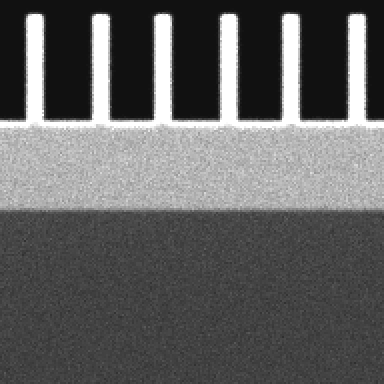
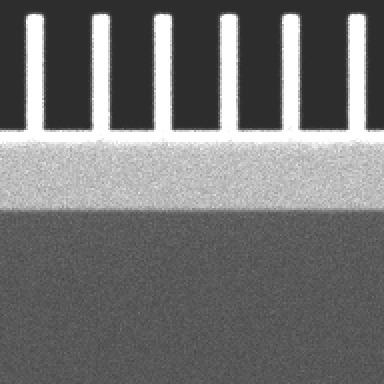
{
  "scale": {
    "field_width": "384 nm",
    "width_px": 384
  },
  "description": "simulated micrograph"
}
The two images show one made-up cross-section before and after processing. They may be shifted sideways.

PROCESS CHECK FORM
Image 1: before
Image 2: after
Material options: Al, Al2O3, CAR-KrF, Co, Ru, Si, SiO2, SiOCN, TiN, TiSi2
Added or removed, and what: removed, TiN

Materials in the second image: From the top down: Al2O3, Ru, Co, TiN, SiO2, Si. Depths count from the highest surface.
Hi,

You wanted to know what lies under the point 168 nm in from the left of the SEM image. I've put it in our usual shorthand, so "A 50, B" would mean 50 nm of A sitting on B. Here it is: Al2O3 40, Ru 56, Co 10, TiN 10, SiO2 78, Si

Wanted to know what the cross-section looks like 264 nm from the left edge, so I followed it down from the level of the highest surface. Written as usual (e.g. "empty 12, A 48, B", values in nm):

empty 116, SiO2 78, Si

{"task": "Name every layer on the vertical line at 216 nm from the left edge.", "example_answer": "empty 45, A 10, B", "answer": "empty 116, SiO2 78, Si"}